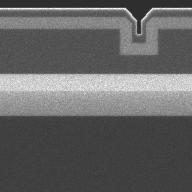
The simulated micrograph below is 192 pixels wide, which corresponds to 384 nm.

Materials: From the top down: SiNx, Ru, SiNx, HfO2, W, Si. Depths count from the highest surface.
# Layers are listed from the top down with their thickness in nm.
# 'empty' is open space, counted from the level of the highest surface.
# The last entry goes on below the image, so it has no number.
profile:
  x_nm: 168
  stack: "SiNx 18, Ru 24, SiNx 90, HfO2 34, W 50, Si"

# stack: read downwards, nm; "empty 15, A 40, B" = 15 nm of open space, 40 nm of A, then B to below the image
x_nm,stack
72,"SiNx 18, Ru 24, SiNx 90, HfO2 34, W 50, Si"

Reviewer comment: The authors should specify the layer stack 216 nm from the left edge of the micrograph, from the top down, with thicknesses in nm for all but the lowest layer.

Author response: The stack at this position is SiNx 18, Ru 24, SiNx 90, HfO2 34, W 50, Si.